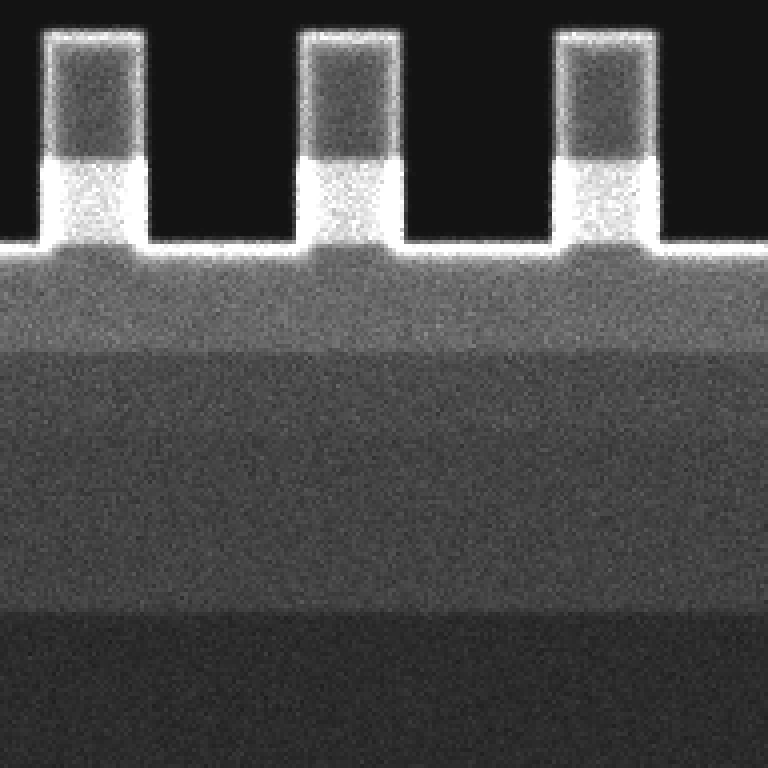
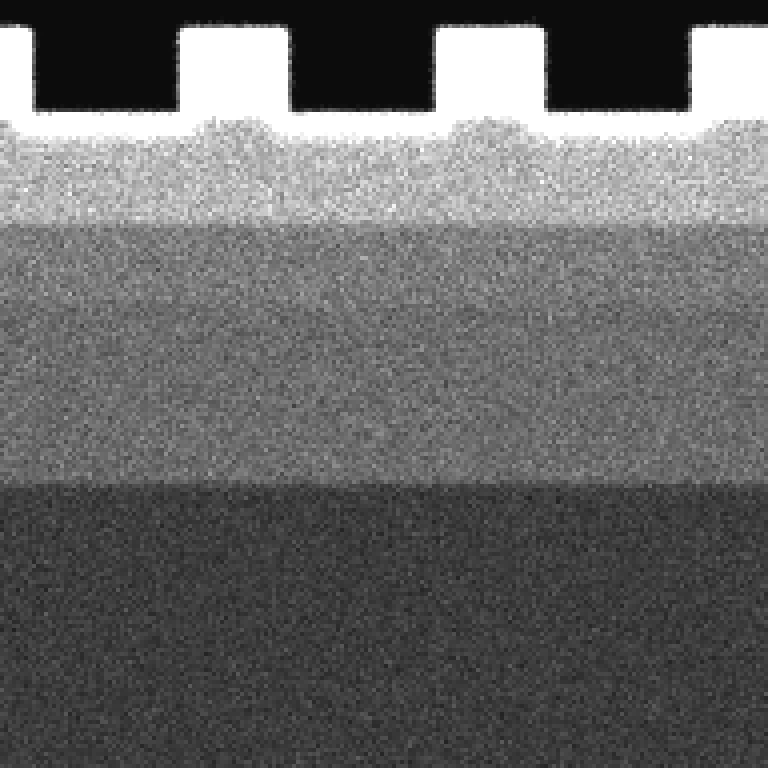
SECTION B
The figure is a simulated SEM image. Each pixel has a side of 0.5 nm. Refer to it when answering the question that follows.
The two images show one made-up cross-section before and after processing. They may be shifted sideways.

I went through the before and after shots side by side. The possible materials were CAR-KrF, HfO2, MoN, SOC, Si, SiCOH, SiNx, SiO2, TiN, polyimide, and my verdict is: removed, SOC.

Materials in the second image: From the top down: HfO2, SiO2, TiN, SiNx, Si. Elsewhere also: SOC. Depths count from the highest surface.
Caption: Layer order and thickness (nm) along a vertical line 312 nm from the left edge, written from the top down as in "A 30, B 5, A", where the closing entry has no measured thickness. empty 42, SiO2 54, TiN 40, SiNx 90, Si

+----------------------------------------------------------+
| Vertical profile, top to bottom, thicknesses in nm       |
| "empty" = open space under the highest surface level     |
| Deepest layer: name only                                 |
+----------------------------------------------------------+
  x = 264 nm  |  HfO2 42, SiO2 54, TiN 40, SiNx 90, Si